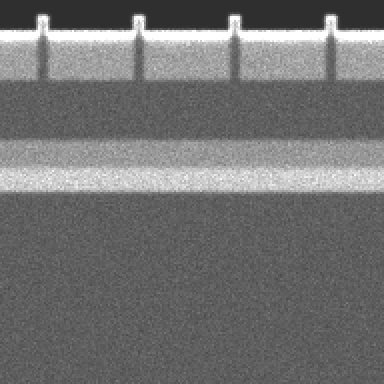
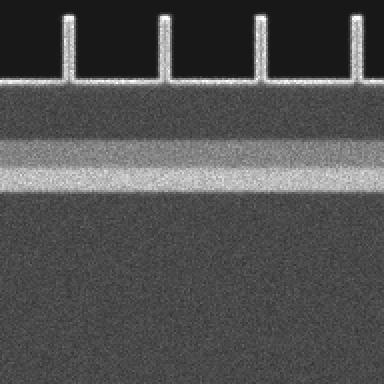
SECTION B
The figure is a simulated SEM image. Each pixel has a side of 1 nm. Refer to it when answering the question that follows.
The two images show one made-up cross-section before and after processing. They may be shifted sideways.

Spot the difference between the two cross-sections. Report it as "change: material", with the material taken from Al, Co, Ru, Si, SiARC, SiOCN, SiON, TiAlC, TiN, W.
removed: SiARC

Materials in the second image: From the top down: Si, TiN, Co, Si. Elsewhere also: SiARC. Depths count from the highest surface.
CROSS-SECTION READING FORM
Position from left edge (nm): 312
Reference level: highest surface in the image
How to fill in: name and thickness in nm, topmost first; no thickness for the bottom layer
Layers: empty 64, Si 60, TiN 28, Co 24, Si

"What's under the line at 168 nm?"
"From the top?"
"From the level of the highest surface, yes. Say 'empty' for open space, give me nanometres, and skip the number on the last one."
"Si 124, TiN 28, Co 24, Si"